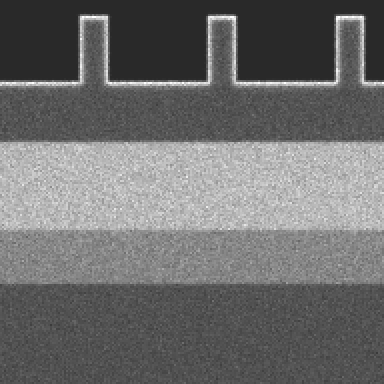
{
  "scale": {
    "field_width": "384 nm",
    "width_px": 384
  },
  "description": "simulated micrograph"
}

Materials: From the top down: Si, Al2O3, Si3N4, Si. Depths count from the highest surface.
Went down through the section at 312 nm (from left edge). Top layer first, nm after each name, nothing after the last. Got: empty 66, Si 60, Al2O3 88, Si3N4 54, Si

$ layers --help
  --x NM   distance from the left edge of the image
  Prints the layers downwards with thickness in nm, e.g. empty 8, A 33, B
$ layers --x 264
empty 66, Si 60, Al2O3 88, Si3N4 54, Si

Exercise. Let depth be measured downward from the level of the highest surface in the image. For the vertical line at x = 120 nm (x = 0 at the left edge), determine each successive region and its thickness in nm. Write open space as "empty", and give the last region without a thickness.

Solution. empty 66, Si 60, Al2O3 88, Si3N4 54, Si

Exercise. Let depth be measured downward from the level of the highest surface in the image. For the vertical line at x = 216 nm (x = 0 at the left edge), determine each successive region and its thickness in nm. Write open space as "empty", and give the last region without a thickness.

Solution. Si 126, Al2O3 88, Si3N4 54, Si